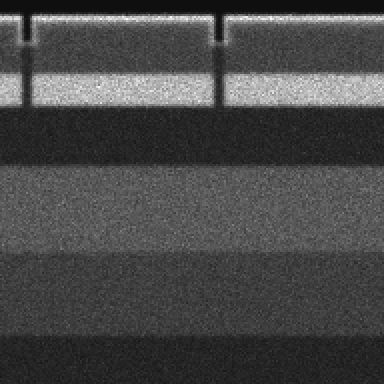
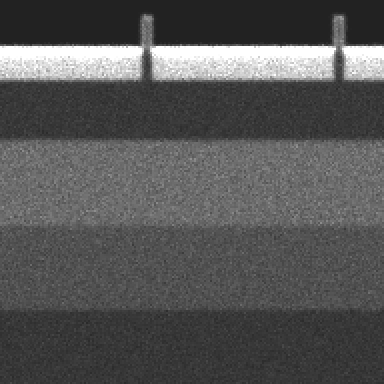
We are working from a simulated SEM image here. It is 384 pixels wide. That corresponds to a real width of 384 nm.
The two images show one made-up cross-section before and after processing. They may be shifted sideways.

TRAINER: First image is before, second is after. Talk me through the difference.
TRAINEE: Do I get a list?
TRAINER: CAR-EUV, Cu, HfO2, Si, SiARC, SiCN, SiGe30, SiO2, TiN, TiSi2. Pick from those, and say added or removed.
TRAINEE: removed: SiARC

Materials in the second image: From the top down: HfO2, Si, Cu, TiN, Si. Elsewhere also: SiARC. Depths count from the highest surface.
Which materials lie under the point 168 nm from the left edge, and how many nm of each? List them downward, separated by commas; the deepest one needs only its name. empty 32, HfO2 32, Si 60, Cu 86, TiN 84, Si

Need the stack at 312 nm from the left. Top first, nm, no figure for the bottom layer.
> empty 32, HfO2 32, Si 60, Cu 86, TiN 84, Si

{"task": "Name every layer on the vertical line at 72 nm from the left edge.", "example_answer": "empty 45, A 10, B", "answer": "empty 32, HfO2 32, Si 60, Cu 86, TiN 84, Si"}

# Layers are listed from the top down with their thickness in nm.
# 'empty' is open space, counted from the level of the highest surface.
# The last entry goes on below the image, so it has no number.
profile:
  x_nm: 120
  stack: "empty 32, HfO2 32, Si 60, Cu 86, TiN 84, Si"